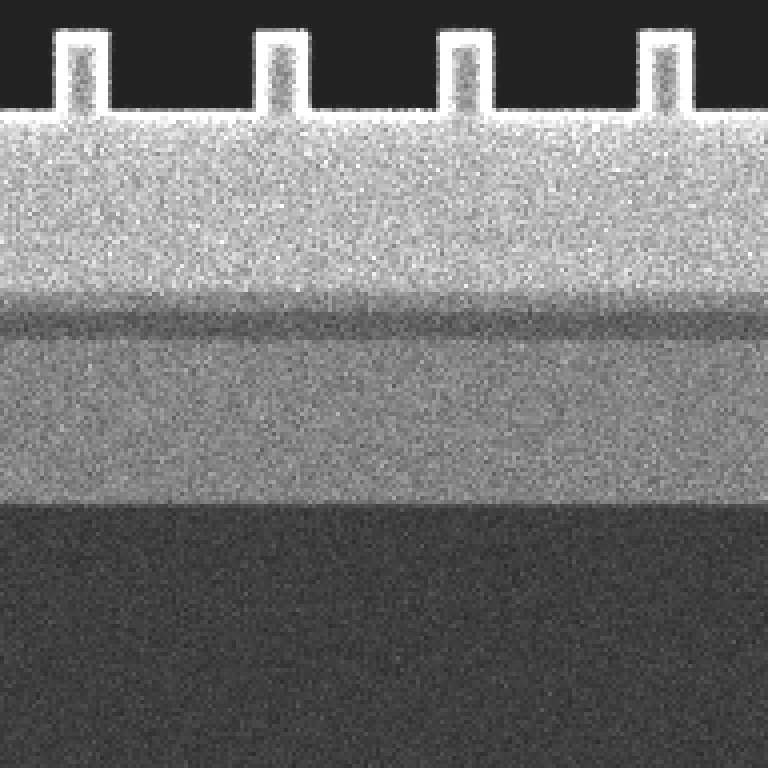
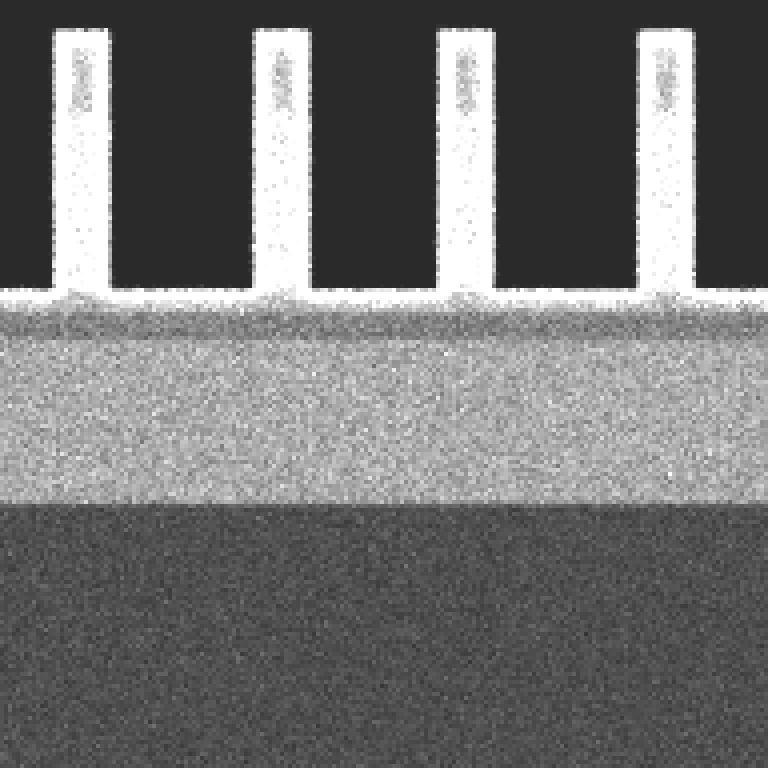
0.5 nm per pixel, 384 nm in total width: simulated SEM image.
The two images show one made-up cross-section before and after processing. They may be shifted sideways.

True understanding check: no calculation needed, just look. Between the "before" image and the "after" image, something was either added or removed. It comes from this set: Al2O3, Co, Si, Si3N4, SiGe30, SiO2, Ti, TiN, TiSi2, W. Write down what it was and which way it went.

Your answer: W (removed)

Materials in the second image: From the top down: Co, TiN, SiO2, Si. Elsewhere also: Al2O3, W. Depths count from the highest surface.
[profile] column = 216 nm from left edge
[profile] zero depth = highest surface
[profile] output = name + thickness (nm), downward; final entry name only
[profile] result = empty 130, Co 10, TiN 14, SiO2 82, Si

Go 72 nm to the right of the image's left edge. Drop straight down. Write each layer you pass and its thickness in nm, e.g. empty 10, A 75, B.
empty 130, Co 10, TiN 14, SiO2 82, Si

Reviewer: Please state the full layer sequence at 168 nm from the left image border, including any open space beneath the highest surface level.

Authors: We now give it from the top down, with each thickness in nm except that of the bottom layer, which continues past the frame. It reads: empty 130, Co 10, TiN 14, SiO2 82, Si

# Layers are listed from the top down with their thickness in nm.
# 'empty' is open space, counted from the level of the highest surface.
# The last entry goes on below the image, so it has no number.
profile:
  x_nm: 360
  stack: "empty 130, Co 10, TiN 14, SiO2 82, Si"